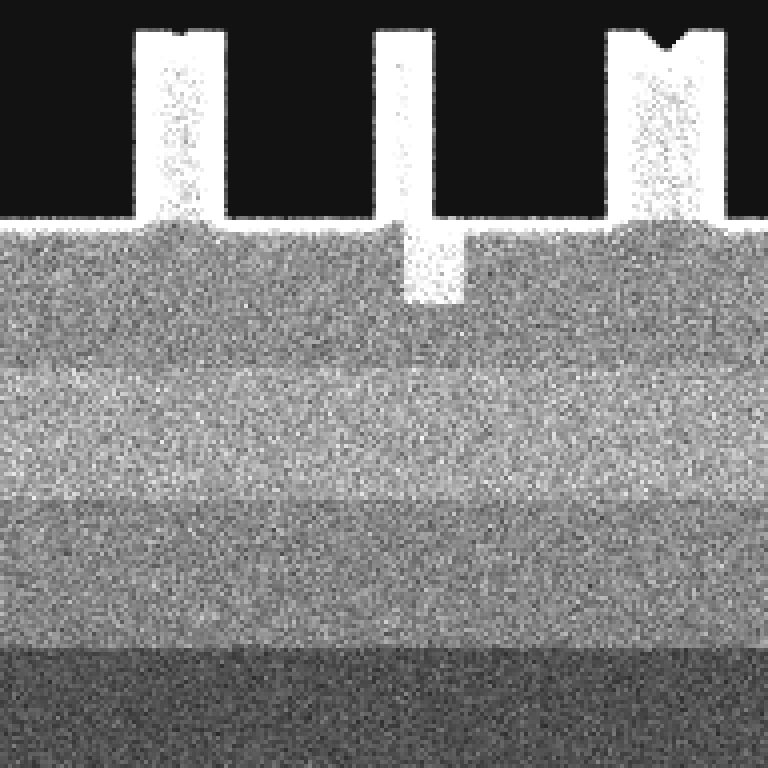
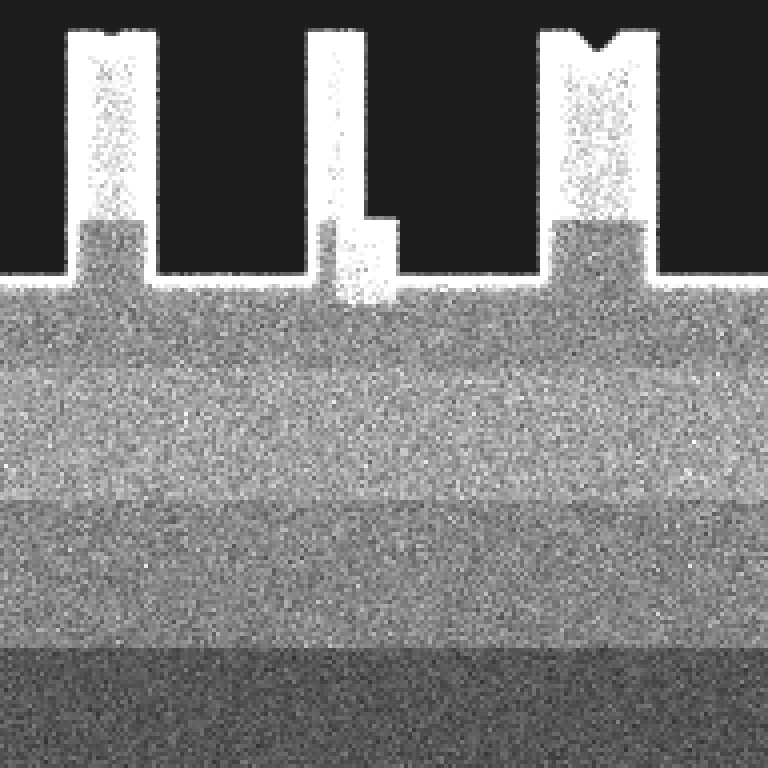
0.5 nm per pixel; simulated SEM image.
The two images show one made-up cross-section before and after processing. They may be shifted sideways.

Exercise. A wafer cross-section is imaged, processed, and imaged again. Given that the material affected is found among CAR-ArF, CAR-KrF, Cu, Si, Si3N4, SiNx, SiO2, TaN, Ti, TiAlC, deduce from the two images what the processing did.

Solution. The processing removed SiNx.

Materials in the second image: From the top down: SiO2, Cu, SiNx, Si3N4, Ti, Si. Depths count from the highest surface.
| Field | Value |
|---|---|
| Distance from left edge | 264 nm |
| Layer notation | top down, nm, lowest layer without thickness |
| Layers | empty 122, SiNx 46, Si3N4 66, Ti 74, Si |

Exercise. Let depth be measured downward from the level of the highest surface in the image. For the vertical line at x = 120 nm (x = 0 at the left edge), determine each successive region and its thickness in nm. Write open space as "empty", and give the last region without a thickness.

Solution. empty 122, SiNx 46, Si3N4 66, Ti 74, Si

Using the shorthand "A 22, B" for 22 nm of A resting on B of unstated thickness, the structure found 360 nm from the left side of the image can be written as empty 122, SiNx 46, Si3N4 66, Ti 74, Si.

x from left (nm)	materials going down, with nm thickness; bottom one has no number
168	SiO2 94, Cu 42, SiNx 32, Si3N4 66, Ti 74, Si